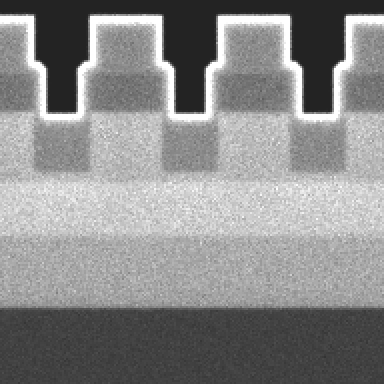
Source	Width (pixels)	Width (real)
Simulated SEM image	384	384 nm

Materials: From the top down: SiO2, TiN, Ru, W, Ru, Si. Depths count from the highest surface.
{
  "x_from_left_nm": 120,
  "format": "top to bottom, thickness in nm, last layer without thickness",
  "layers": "SiO2 58, TiN 38, Ru 70, W 54, Ru 72, Si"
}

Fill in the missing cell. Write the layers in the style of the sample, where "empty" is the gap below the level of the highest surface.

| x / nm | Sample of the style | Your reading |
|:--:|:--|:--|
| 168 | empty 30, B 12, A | empty 48, SiO2 108, Ru 10, W 54, Ru 72, Si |